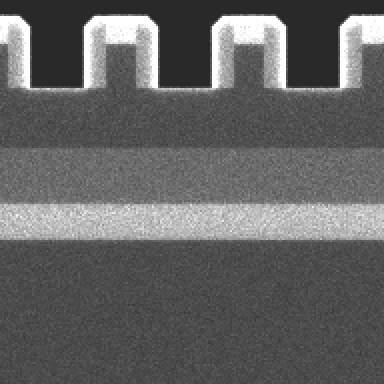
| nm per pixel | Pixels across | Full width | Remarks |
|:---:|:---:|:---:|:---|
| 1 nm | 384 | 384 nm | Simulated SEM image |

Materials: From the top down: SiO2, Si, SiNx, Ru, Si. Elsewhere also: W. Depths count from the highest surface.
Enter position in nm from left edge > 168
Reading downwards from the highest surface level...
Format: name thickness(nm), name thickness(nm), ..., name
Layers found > empty 72, Si 60, SiNx 56, Ru 36, Si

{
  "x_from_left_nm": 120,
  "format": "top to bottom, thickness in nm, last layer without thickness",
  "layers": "W 28, Si 104, SiNx 56, Ru 36, Si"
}